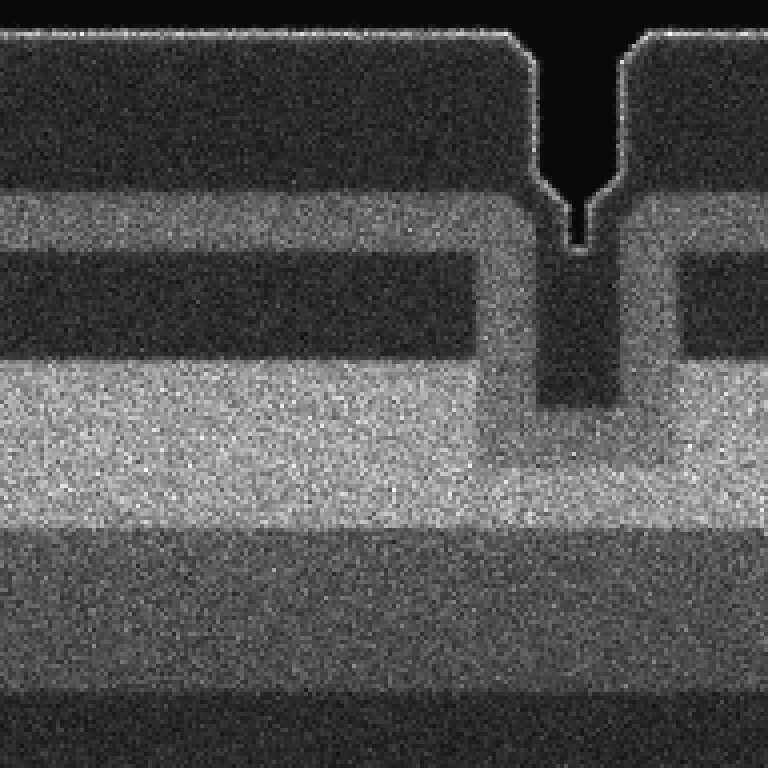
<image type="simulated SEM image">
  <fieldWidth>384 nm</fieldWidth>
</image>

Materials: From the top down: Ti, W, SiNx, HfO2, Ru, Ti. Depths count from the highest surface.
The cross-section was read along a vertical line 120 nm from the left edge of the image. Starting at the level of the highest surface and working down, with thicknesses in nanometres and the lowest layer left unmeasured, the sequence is Ti 80, W 30, SiNx 54, HfO2 84, Ru 82, Ti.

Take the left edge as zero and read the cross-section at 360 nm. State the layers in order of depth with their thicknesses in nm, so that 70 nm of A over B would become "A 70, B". Ti 80, W 30, SiNx 54, HfO2 84, Ru 82, Ti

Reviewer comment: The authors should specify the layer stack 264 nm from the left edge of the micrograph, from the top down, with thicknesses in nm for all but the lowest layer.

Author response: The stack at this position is empty 12, Ti 80, W 126, HfO2 30, Ru 82, Ti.